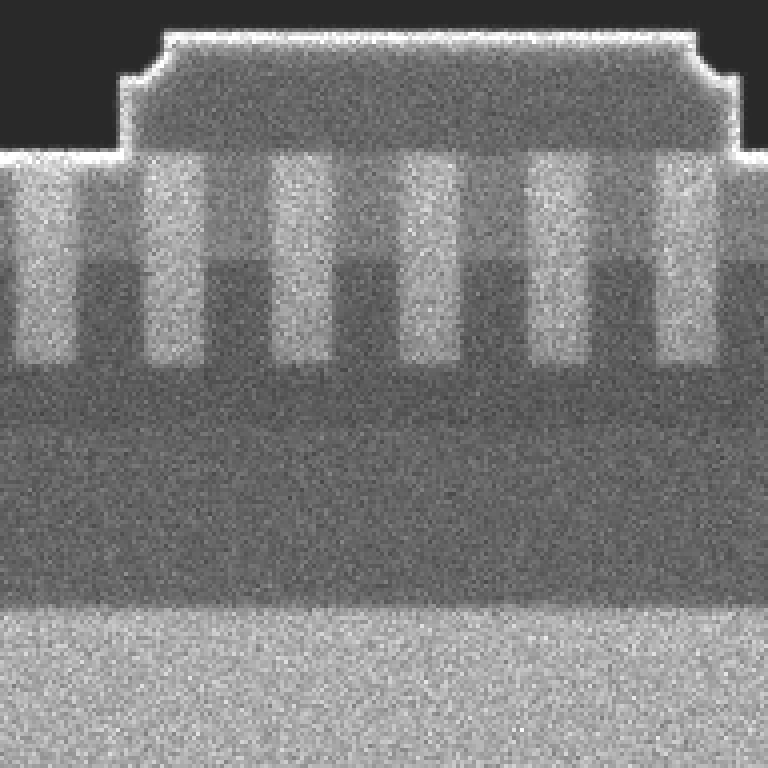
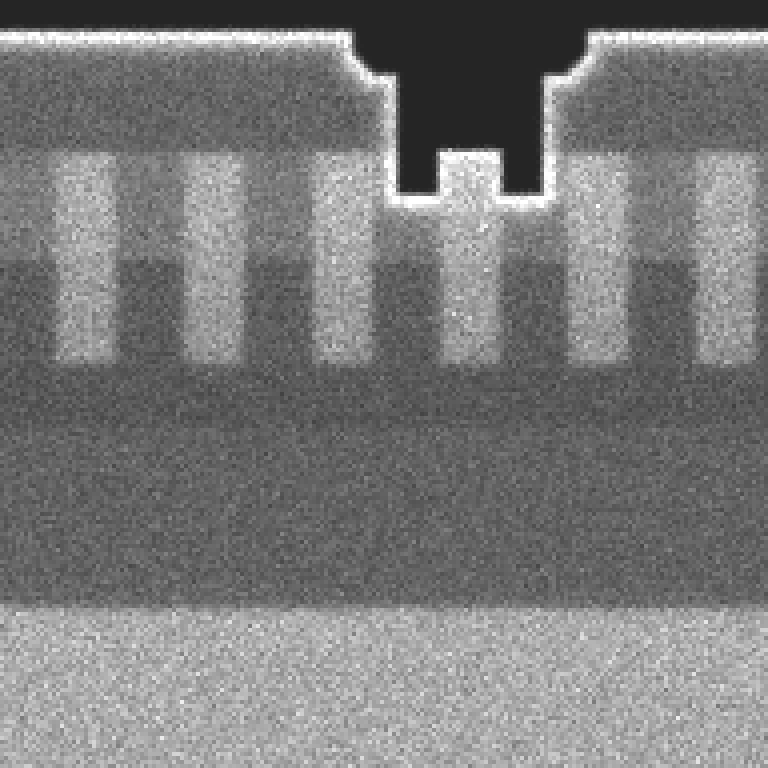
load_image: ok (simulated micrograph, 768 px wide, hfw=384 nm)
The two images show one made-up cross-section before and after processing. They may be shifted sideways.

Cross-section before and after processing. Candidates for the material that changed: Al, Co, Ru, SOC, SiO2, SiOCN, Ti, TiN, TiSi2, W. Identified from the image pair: SiO2 (removed).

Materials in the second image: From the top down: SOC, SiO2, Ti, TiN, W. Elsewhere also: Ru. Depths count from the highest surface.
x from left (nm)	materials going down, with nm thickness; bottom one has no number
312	SOC 60, Ru 106, Ti 32, TiN 90, W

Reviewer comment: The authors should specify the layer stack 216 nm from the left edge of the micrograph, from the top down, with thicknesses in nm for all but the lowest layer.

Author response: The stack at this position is empty 82, SiO2 32, Ti 84, TiN 90, W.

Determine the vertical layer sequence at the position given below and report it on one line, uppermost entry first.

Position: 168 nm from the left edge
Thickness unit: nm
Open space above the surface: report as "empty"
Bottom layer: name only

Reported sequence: SOC 60, Ru 106, Ti 32, TiN 90, W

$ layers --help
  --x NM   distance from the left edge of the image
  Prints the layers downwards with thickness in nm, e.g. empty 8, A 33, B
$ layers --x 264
empty 82, SiO2 32, Ti 84, TiN 90, W